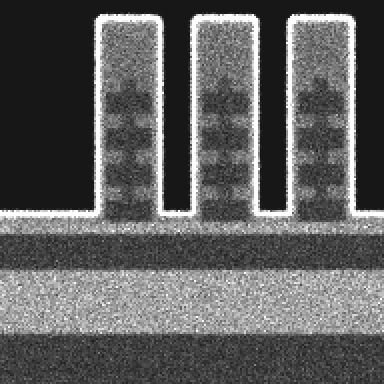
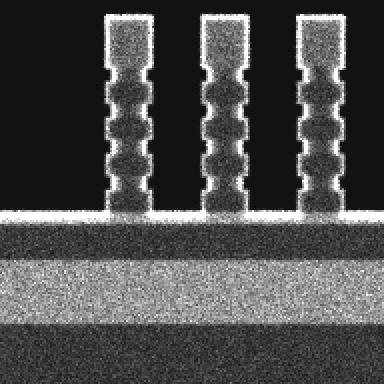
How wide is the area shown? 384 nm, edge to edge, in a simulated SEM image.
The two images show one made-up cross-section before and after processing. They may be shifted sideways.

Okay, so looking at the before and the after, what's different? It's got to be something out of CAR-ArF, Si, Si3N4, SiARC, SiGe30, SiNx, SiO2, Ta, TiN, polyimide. Si3N4, removed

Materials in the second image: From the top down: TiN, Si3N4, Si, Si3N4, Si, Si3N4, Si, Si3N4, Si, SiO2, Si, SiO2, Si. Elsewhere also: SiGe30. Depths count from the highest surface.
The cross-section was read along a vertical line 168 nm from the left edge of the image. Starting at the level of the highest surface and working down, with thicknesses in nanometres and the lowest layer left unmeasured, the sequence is empty 196, SiO2 12, Si 36, SiO2 64, Si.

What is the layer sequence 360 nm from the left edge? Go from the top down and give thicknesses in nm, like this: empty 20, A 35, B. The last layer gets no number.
empty 196, SiO2 12, Si 36, SiO2 64, Si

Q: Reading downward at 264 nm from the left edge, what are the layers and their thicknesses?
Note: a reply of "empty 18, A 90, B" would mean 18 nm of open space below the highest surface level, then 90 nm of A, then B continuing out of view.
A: empty 196, SiO2 12, Si 36, SiO2 64, Si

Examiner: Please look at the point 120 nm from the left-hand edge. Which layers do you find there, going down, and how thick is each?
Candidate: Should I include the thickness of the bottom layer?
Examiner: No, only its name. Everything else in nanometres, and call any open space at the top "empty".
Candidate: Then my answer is TiN 52, Si3N4 14, Si 22, Si3N4 14, Si 22, Si3N4 14, Si 22, Si3N4 14, Si 22, SiO2 12, Si 36, SiO2 64, Si